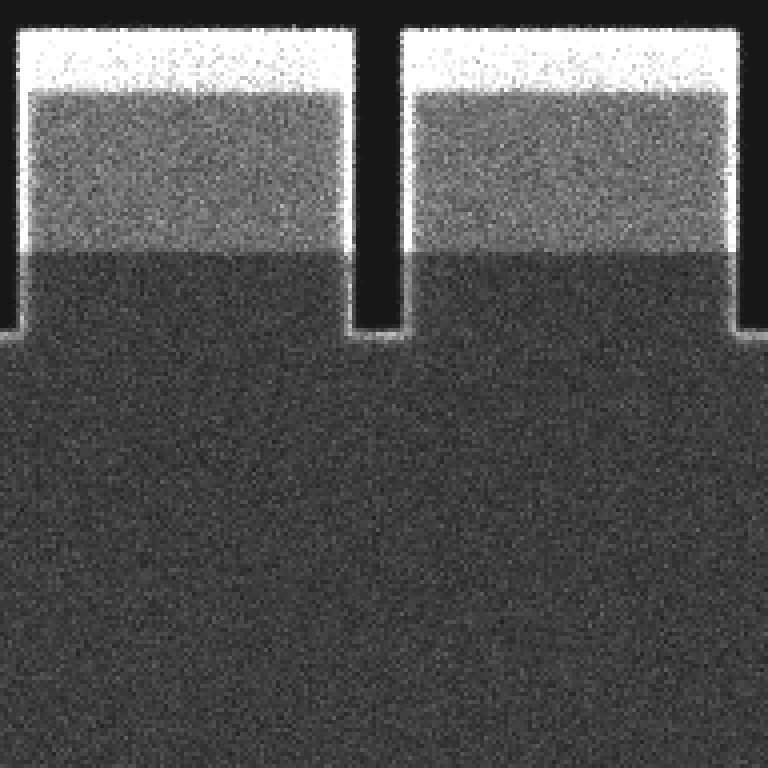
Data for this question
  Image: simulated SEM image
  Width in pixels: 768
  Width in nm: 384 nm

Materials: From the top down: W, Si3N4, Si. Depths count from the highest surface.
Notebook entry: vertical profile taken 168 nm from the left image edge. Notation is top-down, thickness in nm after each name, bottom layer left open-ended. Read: W 30, Si3N4 80, Si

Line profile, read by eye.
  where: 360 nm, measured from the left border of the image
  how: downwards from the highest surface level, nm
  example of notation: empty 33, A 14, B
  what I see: W 30, Si3N4 80, Si